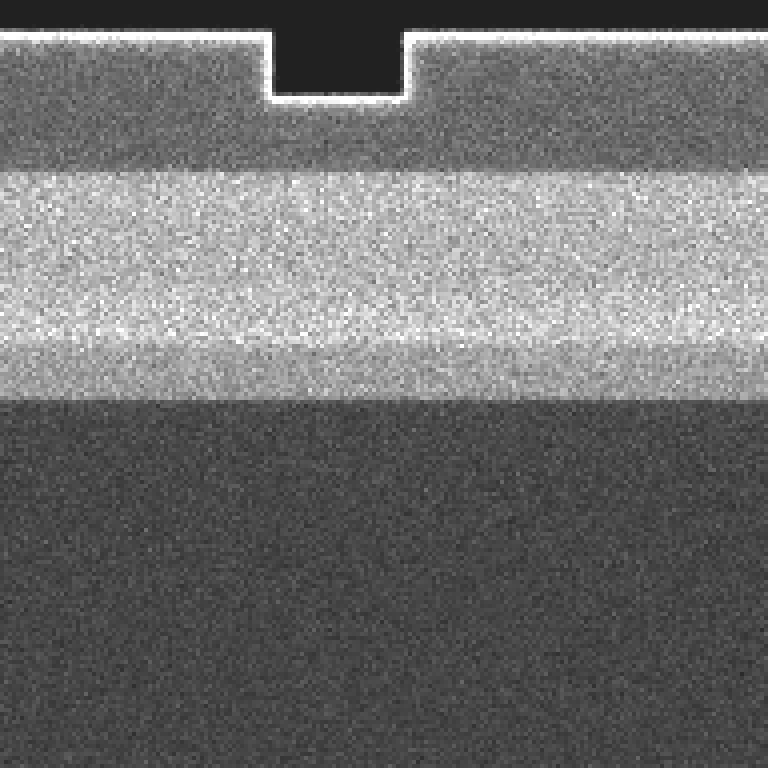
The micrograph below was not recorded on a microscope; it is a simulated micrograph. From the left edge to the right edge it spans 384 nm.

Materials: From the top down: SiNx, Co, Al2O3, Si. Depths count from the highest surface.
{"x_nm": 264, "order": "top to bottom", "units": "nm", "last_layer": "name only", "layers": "SiNx 70, Co 86, Al2O3 28, Si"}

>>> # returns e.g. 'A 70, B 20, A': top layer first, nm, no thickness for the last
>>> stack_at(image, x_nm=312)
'SiNx 70, Co 86, Al2O3 28, Si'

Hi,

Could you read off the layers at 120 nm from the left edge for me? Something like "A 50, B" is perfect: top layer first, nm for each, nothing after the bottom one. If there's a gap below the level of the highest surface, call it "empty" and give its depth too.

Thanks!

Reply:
SiNx 70, Co 86, Al2O3 28, Si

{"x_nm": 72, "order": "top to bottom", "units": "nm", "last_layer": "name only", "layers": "SiNx 70, Co 86, Al2O3 28, Si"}